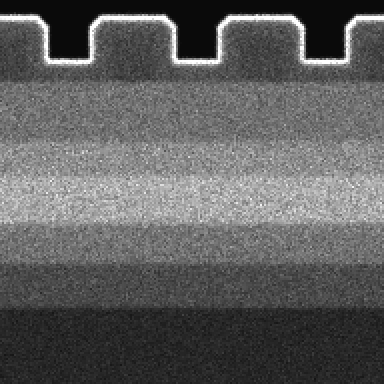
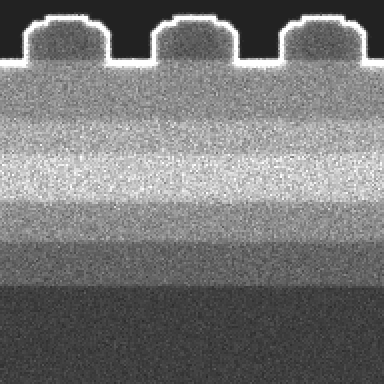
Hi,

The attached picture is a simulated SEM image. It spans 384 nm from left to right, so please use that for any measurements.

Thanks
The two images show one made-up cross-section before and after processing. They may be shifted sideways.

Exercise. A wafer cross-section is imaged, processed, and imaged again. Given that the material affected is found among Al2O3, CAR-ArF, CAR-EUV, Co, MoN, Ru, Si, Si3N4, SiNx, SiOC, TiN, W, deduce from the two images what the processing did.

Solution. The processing removed Si3N4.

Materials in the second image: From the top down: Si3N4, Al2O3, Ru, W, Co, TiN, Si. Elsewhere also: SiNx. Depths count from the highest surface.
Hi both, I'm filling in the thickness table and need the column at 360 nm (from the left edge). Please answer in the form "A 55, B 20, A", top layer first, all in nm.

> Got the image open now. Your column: empty 12, Si3N4 32, Al2O3 60, Ru 34, W 48, Co 40, TiN 44, Si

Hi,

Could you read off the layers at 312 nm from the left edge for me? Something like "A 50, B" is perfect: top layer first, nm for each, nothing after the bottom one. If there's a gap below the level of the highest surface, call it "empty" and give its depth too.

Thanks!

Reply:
SiNx 44, Al2O3 60, Ru 34, W 48, Co 40, TiN 44, Si